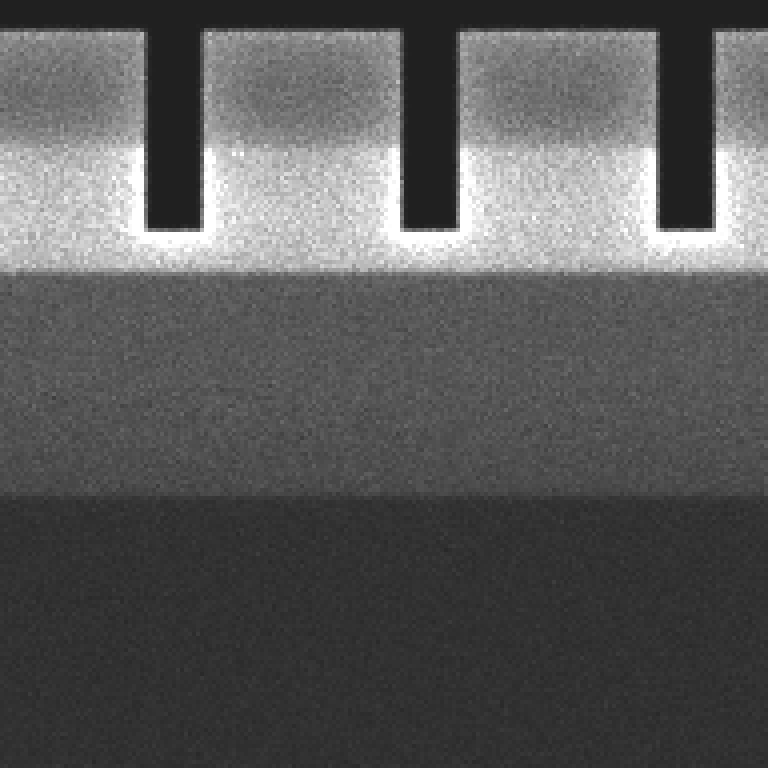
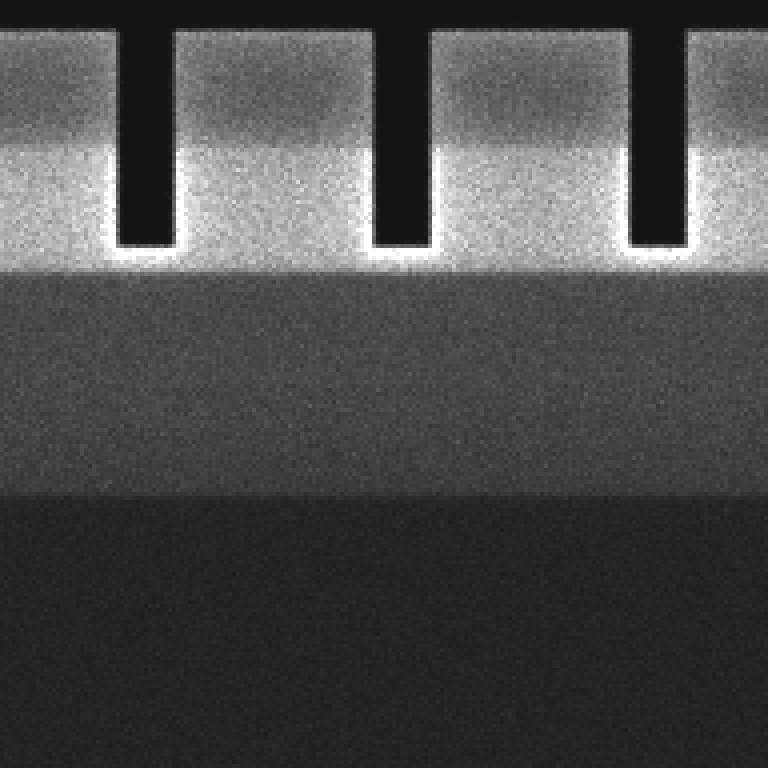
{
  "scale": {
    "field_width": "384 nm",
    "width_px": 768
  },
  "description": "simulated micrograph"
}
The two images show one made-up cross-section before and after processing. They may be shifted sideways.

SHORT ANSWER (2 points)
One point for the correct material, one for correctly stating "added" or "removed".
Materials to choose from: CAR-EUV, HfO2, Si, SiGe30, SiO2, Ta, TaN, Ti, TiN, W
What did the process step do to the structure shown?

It removed HfO2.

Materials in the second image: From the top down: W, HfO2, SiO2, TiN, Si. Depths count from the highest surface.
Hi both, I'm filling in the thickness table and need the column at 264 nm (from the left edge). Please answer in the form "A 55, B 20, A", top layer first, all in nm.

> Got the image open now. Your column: W 58, HfO2 62, SiO2 56, TiN 56, Si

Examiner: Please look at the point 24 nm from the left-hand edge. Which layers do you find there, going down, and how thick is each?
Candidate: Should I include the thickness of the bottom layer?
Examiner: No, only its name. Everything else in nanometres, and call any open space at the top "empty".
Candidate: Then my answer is W 58, HfO2 62, SiO2 56, TiN 56, Si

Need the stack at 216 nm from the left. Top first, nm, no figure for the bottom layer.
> W 58, HfO2 62, SiO2 56, TiN 56, Si